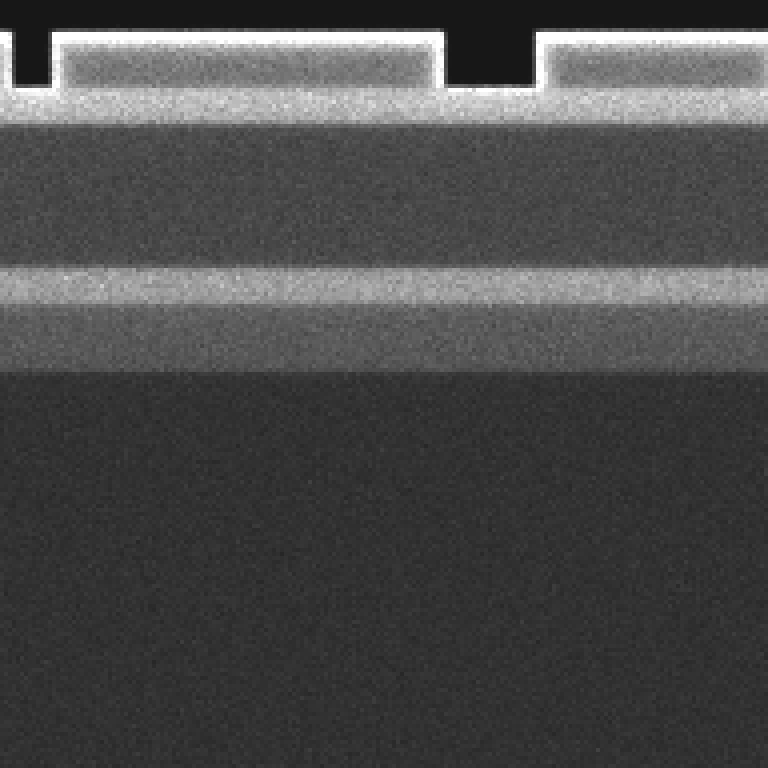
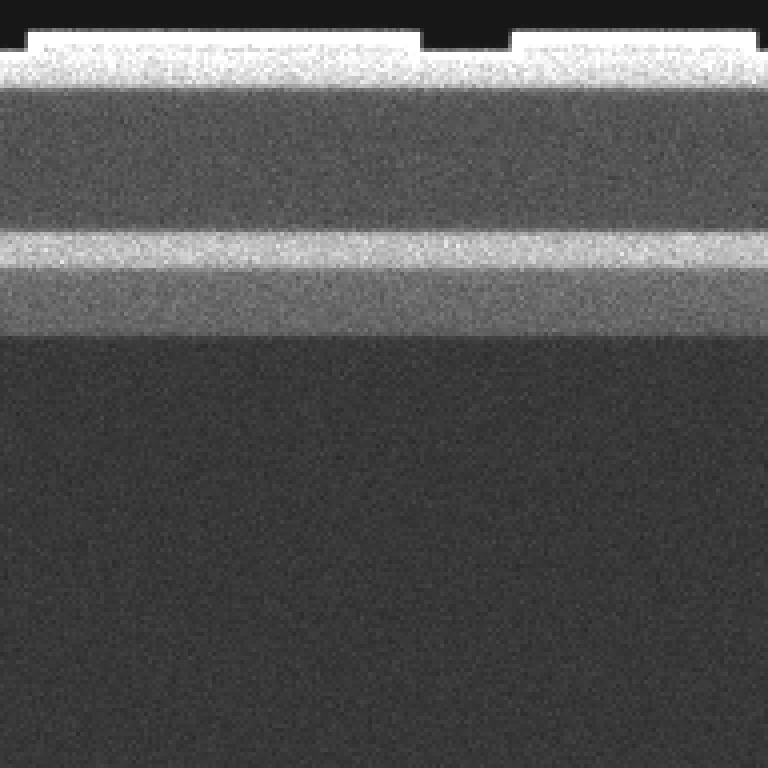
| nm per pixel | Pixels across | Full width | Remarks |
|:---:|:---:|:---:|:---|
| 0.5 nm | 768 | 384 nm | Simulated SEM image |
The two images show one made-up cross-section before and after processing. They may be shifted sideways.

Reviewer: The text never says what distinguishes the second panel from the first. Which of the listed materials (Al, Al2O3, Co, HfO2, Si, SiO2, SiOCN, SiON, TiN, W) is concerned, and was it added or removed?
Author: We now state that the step removed SiO2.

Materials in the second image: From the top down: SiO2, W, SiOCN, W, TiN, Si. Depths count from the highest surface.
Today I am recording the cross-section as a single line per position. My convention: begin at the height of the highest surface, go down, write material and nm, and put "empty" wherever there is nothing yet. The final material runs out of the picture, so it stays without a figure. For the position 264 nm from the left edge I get SiO2 10, W 18, SiOCN 72, W 18, TiN 34, Si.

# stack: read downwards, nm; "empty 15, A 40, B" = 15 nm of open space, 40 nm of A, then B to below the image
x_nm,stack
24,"SiO2 10, W 18, SiOCN 72, W 18, TiN 34, Si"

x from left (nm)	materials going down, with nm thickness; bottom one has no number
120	SiO2 10, W 18, SiOCN 72, W 18, TiN 34, Si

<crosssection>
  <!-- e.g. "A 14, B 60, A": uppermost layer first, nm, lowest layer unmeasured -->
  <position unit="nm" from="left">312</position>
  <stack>SiO2 10, W 18, SiOCN 72, W 18, TiN 34, Si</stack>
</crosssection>